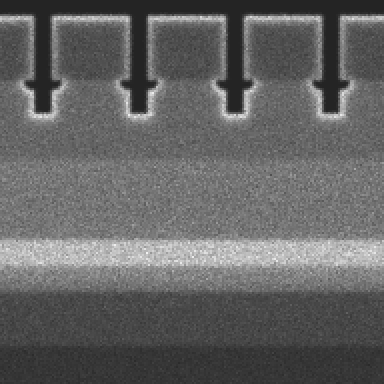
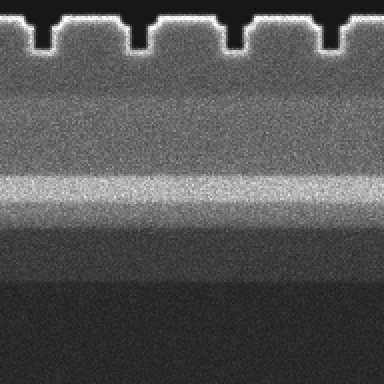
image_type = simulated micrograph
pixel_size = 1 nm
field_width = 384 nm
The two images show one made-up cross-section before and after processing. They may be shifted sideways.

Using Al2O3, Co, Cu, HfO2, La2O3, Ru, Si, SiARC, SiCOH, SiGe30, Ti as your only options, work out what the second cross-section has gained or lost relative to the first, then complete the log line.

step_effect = removed SiARC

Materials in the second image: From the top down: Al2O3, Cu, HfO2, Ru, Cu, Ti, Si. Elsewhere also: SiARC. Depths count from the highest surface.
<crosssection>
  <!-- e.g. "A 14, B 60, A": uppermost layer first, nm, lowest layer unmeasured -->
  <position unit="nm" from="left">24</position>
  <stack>empty 6, Al2O3 74, Cu 80, HfO2 26, Ru 18, Cu 8, Ti 54, Si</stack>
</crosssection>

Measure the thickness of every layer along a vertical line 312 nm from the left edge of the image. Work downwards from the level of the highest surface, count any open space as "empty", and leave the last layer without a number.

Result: empty 6, Al2O3 74, Cu 80, HfO2 26, Ru 18, Cu 8, Ti 54, Si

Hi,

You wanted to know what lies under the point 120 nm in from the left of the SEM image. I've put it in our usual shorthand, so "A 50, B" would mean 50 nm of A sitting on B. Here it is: empty 6, Al2O3 74, Cu 80, HfO2 26, Ru 18, Cu 8, Ti 54, Si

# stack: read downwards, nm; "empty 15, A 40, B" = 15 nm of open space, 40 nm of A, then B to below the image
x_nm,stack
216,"empty 6, Al2O3 74, Cu 80, HfO2 26, Ru 18, Cu 8, Ti 54, Si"